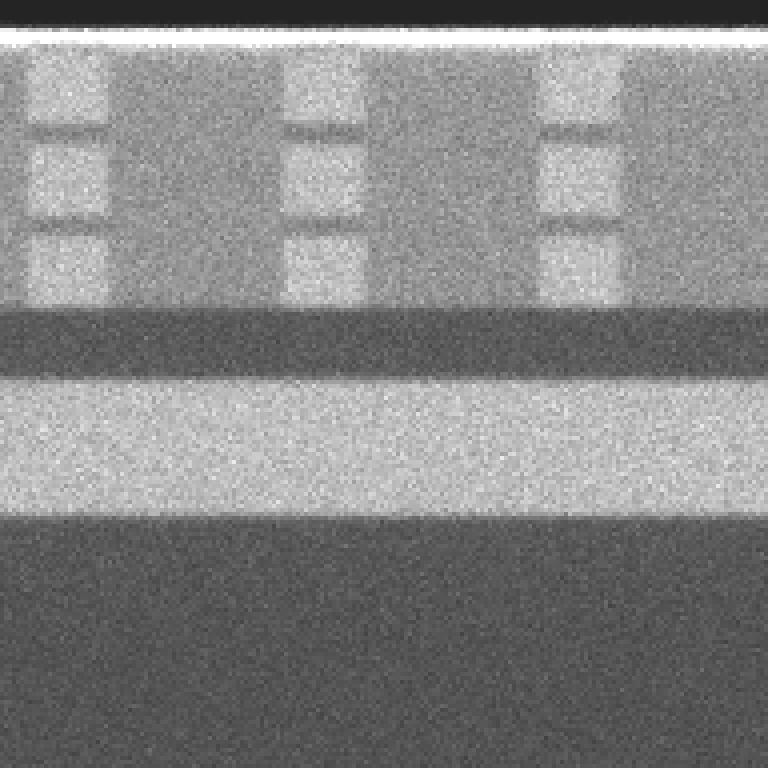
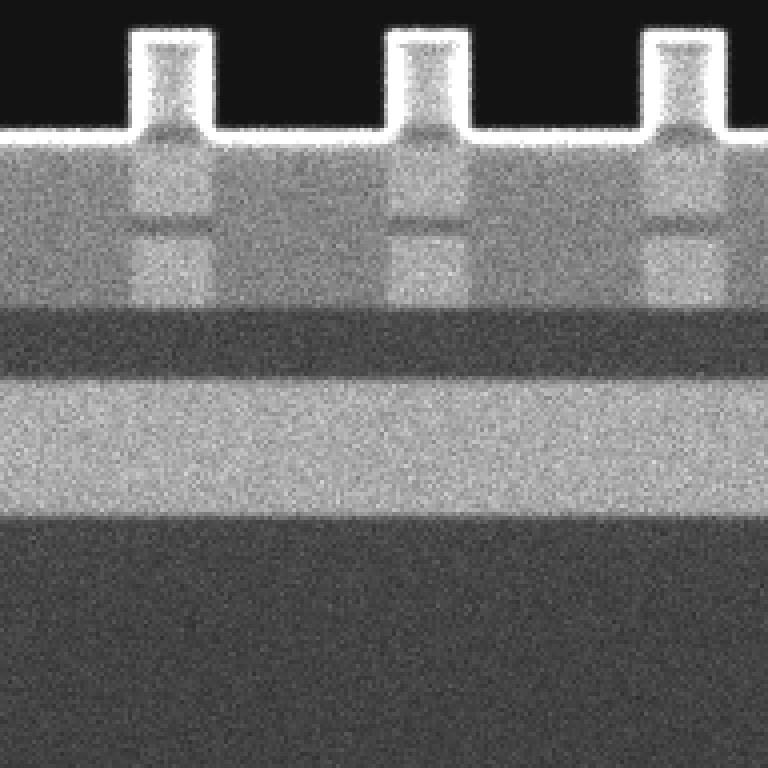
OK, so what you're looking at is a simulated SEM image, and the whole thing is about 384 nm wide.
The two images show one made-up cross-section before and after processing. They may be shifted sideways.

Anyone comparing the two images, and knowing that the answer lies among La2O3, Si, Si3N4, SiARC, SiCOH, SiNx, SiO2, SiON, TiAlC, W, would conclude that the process removed Si3N4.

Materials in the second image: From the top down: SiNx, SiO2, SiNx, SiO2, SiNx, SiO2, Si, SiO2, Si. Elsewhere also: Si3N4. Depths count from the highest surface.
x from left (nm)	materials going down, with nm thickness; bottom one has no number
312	empty 50, Si3N4 88, Si 36, SiO2 68, Si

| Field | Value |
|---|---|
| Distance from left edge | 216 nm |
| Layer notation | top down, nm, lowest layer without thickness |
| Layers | SiNx 10, SiO2 36, SiNx 10, SiO2 36, SiNx 10, SiO2 36, Si 36, SiO2 68, Si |